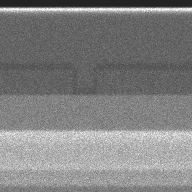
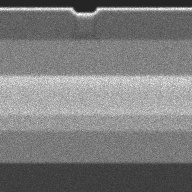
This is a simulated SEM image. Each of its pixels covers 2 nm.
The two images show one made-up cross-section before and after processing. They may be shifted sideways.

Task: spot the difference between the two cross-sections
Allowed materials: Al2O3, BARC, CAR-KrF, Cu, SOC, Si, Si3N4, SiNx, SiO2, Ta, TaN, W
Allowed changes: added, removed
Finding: removed SOC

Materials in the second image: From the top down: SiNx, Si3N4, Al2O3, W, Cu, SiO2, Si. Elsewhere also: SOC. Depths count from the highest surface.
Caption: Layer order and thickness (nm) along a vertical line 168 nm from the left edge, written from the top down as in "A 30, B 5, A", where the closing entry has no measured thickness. empty 10, SOC 40, SiNx 14, Al2O3 72, W 78, Cu 32, SiO2 64, Si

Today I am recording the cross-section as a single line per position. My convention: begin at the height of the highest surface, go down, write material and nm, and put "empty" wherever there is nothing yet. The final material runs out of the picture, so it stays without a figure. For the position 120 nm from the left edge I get SiNx 14, Si3N4 50, Al2O3 72, W 78, Cu 32, SiO2 64, Si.